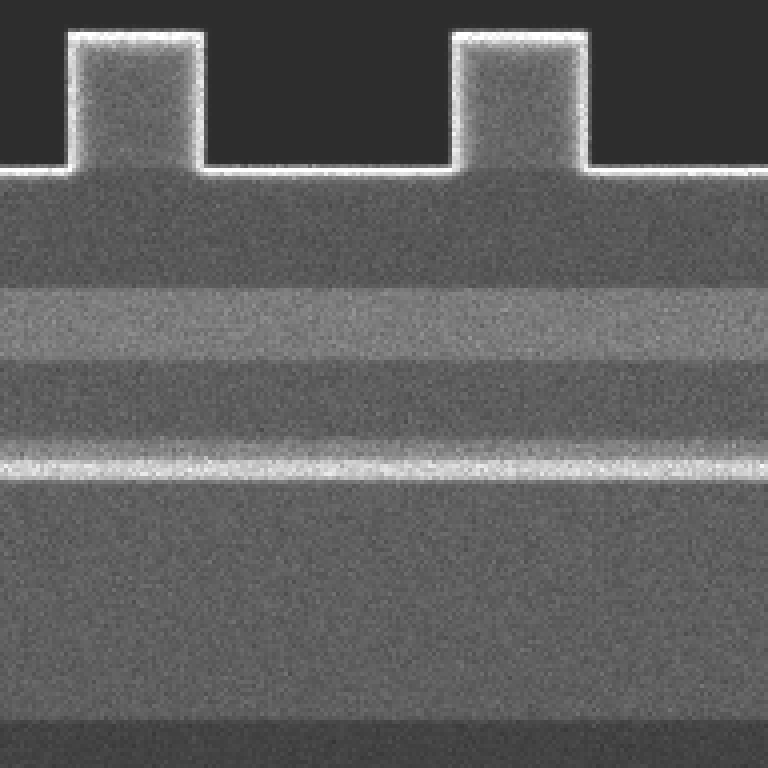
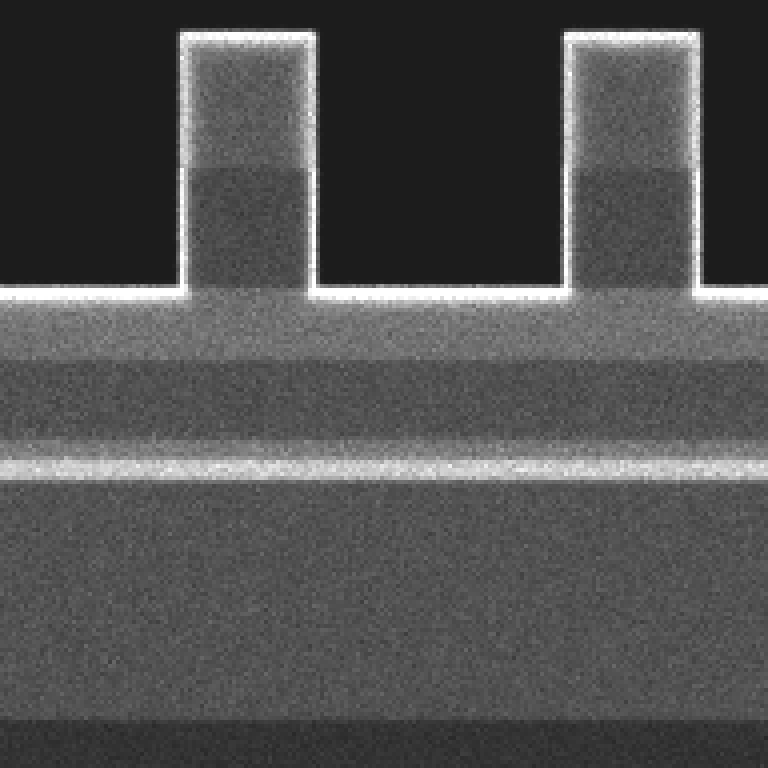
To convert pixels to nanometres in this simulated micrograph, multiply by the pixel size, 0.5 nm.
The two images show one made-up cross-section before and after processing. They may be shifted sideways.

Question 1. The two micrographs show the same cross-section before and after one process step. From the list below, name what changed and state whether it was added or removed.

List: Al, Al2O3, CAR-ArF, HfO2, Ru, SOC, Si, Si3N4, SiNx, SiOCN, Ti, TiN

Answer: SiNx, removed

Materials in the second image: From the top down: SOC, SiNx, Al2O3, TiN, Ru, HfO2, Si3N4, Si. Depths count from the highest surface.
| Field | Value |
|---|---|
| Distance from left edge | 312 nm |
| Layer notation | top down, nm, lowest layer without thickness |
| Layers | SOC 68, SiNx 60, Al2O3 36, TiN 40, Ru 10, HfO2 10, Si3N4 120, Si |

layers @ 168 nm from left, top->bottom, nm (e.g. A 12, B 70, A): empty 128, Al2O3 36, TiN 40, Ru 10, HfO2 10, Si3N4 120, Si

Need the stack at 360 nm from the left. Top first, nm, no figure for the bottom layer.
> empty 128, Al2O3 36, TiN 40, Ru 10, HfO2 10, Si3N4 120, Si